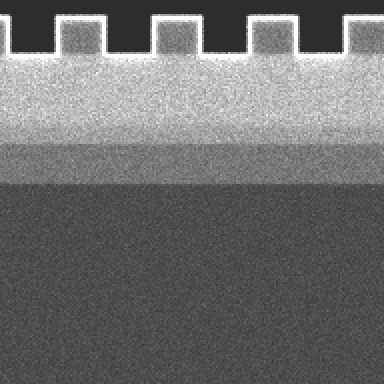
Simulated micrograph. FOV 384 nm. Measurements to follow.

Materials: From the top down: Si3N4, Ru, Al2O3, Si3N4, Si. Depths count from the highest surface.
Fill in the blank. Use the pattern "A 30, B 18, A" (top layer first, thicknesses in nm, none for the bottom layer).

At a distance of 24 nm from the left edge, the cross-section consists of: empty 38, Ru 72, Al2O3 18, Si3N4 40, Si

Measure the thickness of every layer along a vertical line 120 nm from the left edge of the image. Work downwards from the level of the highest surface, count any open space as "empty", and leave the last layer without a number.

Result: empty 38, Ru 72, Al2O3 18, Si3N4 40, Si